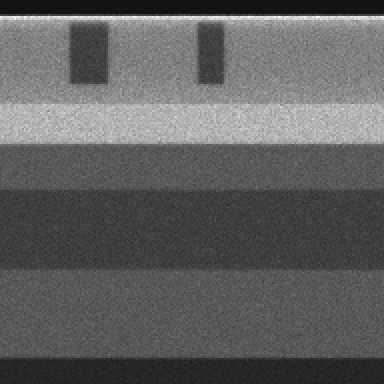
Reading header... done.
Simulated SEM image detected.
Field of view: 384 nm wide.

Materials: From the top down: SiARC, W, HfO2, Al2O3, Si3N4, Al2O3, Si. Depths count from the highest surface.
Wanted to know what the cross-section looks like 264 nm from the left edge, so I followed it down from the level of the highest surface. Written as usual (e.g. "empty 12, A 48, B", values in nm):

SiARC 6, W 82, HfO2 40, Al2O3 46, Si3N4 80, Al2O3 88, Si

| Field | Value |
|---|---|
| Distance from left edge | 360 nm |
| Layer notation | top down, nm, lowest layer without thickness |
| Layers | SiARC 6, W 82, HfO2 40, Al2O3 46, Si3N4 80, Al2O3 88, Si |